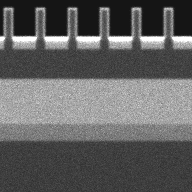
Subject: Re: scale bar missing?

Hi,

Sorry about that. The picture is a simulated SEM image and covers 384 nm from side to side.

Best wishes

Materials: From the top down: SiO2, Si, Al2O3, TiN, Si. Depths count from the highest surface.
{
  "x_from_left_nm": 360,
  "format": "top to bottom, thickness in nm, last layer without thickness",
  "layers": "empty 58, SiO2 24, Si 60, Al2O3 90, TiN 34, Si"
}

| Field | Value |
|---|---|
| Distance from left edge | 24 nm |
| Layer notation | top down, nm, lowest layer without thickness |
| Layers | Si 142, Al2O3 90, TiN 34, Si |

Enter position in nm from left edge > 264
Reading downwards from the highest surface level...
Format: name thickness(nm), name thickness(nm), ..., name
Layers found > Si 142, Al2O3 90, TiN 34, Si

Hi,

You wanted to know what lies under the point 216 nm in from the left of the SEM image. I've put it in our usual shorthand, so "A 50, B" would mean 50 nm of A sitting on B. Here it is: Si 142, Al2O3 90, TiN 34, Si